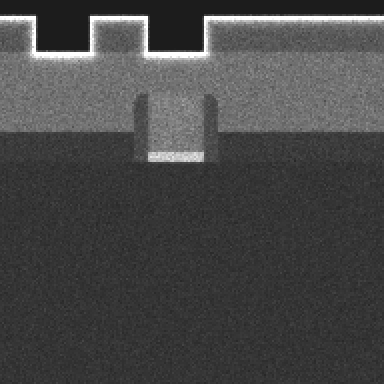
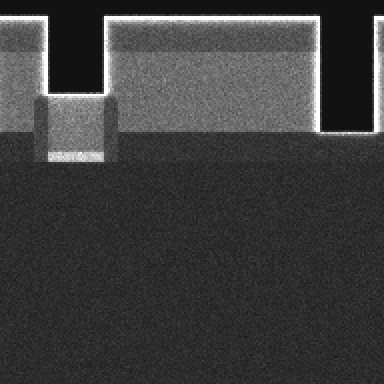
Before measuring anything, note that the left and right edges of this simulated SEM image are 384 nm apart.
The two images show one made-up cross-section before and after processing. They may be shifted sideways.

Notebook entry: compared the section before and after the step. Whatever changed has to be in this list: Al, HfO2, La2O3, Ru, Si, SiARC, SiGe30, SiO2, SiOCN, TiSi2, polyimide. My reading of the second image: SiO2 removed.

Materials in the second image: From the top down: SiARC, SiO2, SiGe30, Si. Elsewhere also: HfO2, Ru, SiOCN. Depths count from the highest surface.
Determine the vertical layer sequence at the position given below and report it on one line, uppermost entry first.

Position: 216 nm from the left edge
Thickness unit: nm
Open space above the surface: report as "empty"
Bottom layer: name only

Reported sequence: SiARC 36, SiO2 80, SiGe30 30, Si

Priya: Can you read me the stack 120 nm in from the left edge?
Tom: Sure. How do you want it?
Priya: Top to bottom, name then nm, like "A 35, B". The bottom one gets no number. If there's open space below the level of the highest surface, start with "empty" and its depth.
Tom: SiARC 36, SiO2 80, SiGe30 30, Si